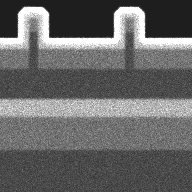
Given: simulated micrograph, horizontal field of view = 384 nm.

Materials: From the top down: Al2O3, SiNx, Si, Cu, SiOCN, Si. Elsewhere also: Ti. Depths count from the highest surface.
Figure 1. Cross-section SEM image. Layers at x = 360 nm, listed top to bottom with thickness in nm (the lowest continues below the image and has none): empty 62, Al2O3 20, SiNx 40, Si 60, Cu 36, SiOCN 66, Si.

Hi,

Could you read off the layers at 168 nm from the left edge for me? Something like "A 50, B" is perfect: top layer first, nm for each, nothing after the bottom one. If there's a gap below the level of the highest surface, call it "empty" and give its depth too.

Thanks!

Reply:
empty 62, Al2O3 20, SiNx 40, Si 60, Cu 36, SiOCN 66, Si